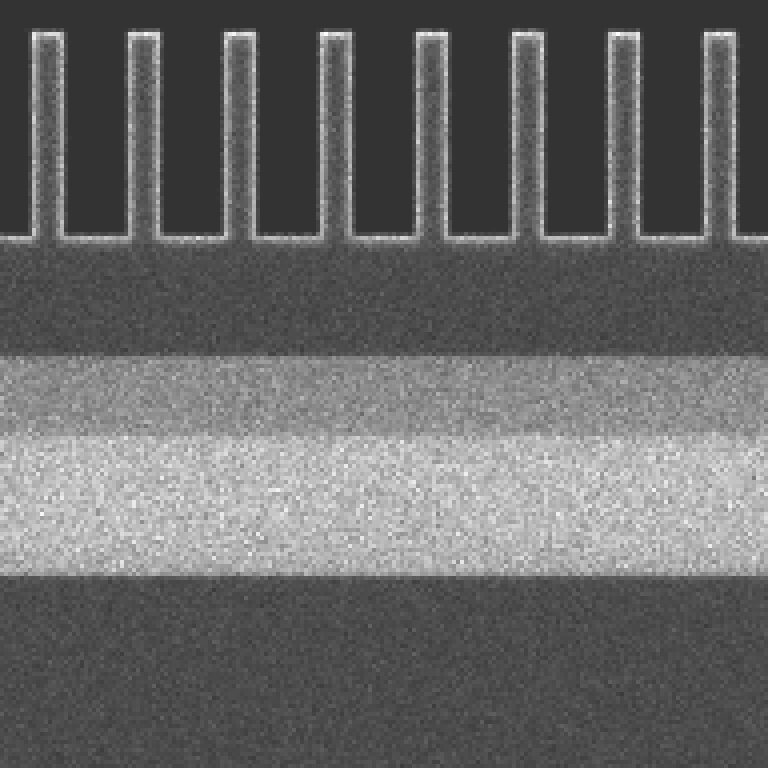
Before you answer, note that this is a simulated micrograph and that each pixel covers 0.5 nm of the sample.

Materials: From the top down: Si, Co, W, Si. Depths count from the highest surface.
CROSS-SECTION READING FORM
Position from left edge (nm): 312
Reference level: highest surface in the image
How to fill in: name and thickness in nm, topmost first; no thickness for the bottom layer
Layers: Si 162, Co 40, W 70, Si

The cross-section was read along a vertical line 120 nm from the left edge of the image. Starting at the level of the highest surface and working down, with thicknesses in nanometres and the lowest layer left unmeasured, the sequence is Si 162, Co 40, W 70, Si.